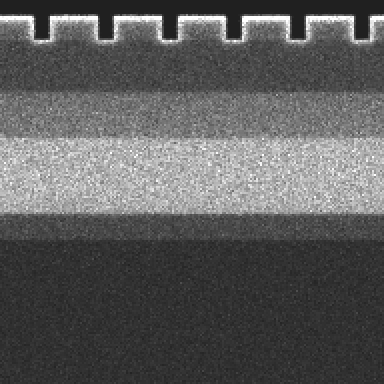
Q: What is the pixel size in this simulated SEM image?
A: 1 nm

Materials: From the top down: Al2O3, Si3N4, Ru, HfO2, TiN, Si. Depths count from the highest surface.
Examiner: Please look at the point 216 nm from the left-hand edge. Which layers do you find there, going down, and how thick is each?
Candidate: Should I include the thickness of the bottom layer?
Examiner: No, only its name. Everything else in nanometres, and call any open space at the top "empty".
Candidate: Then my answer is Al2O3 24, Si3N4 52, Ru 46, HfO2 76, TiN 26, Si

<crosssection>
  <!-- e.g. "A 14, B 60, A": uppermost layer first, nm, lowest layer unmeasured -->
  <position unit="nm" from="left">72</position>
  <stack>Al2O3 24, Si3N4 52, Ru 46, HfO2 76, TiN 26, Si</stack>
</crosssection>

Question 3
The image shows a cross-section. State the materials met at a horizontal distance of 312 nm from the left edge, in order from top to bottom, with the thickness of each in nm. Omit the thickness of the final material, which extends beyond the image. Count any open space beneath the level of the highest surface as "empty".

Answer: Al2O3 24, Si3N4 52, Ru 46, HfO2 76, TiN 26, Si